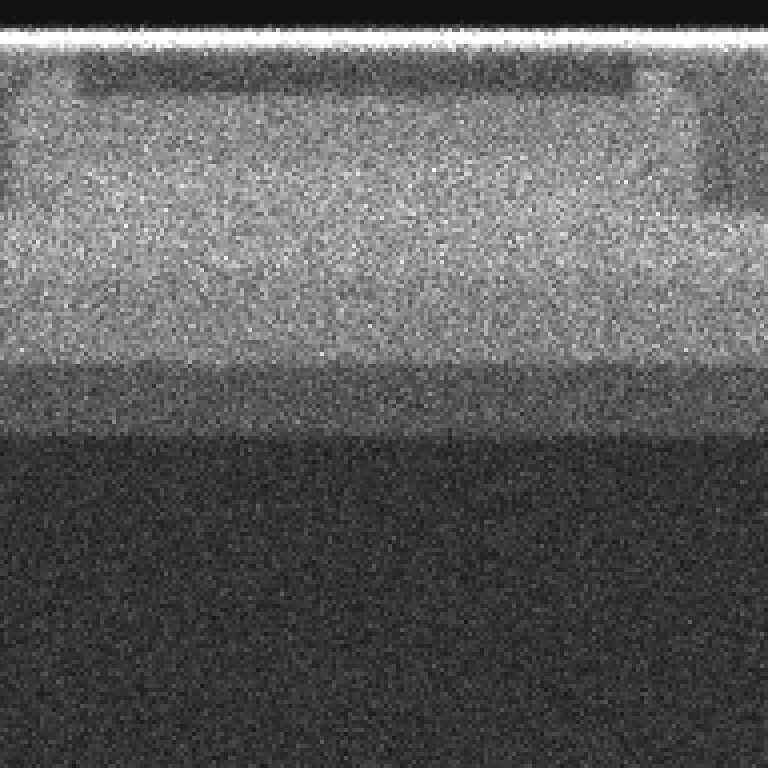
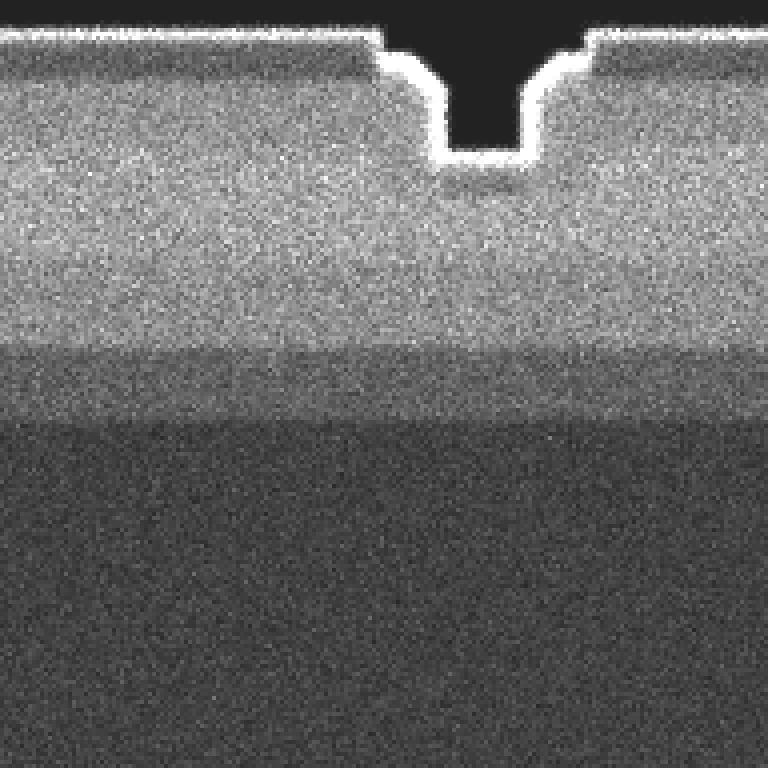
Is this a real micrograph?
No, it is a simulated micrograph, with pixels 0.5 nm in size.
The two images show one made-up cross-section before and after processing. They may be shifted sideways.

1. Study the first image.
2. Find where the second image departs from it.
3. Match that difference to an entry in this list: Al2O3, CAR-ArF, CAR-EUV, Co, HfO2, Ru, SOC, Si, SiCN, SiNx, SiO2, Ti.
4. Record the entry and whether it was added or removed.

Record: SOC / removed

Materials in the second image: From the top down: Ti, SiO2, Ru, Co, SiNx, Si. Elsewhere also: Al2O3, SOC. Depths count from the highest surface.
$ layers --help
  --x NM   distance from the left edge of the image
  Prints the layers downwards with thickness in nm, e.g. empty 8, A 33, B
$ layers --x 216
empty 24, Al2O3 58, Ru 32, Co 44, SiNx 36, Si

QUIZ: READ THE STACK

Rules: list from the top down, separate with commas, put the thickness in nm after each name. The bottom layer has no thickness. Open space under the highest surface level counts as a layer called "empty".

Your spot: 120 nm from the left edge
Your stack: Ti 24, SiO2 32, Ru 58, Co 44, SiNx 36, Si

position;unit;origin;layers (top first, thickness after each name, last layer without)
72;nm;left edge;Ti 24, SiO2 32, Ru 58, Co 44, SiNx 36, Si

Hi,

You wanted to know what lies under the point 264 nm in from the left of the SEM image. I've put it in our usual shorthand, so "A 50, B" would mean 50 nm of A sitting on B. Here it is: empty 26, Al2O3 56, Ru 32, Co 44, SiNx 36, Si